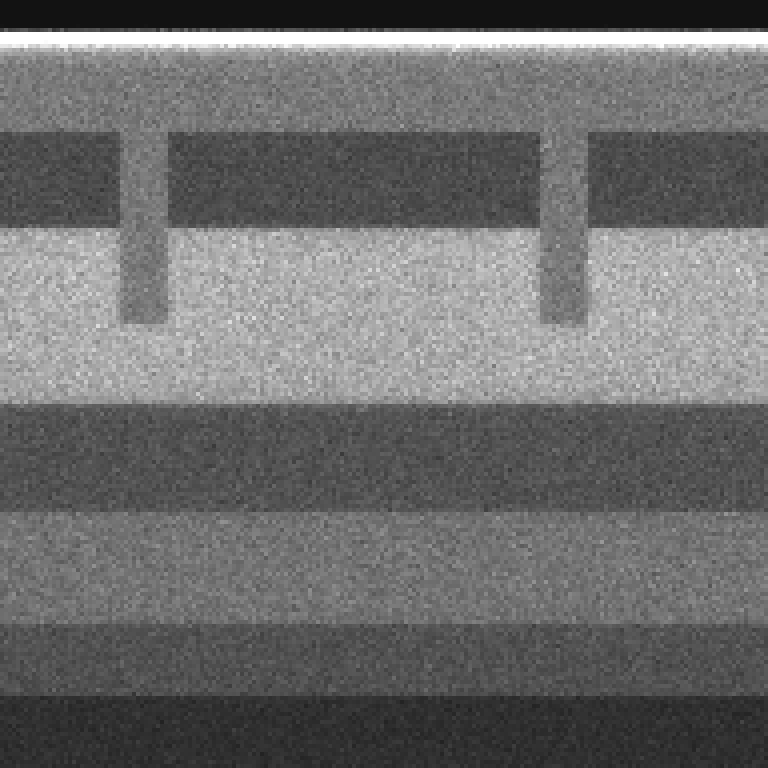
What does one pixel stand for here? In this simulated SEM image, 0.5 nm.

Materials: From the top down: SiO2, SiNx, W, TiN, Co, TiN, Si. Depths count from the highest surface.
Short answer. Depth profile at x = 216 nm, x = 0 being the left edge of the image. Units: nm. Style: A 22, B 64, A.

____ SiO2 50, SiNx 48, W 88, TiN 54, Co 56, TiN 36, Si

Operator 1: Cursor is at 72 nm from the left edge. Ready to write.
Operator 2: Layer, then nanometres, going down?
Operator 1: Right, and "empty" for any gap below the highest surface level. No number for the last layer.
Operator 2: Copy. SiO2 146, W 40, TiN 54, Co 56, TiN 36, Si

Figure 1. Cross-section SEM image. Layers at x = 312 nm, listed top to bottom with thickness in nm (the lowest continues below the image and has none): SiO2 50, SiNx 48, W 88, TiN 54, Co 56, TiN 36, Si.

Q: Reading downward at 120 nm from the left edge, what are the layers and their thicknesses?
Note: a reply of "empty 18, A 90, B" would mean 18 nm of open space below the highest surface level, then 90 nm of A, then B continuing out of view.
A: SiO2 50, SiNx 48, W 88, TiN 54, Co 56, TiN 36, Si